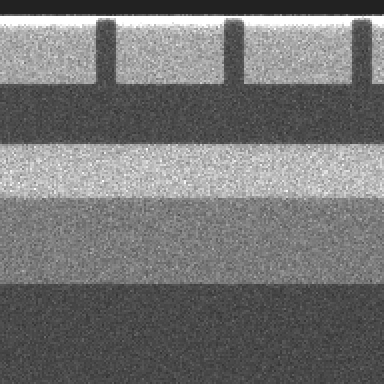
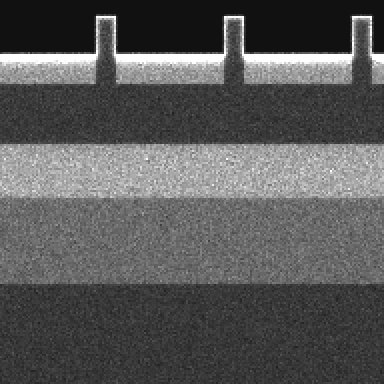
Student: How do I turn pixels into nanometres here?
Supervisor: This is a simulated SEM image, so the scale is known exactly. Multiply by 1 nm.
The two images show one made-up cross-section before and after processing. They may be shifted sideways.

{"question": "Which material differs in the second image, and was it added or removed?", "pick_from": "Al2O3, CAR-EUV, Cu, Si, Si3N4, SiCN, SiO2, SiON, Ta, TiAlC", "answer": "SiO2, removed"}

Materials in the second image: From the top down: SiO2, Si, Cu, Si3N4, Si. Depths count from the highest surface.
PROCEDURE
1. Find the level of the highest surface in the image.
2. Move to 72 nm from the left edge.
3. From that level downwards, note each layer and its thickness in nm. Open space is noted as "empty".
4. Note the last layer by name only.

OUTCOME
empty 38, SiO2 30, Si 60, Cu 54, Si3N4 86, Si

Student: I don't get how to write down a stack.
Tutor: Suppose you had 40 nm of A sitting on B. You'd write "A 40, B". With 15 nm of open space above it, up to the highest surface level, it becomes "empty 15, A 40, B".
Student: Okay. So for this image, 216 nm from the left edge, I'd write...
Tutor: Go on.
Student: empty 38, SiO2 30, Si 60, Cu 54, Si3N4 86, Si